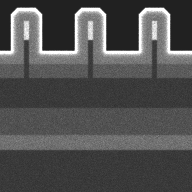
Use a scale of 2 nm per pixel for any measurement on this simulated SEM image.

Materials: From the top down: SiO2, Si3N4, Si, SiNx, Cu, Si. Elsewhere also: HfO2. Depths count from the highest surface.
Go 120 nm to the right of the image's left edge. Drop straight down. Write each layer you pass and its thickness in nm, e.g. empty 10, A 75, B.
empty 86, SiO2 26, Si3N4 28, Si 60, SiNx 54, Cu 30, Si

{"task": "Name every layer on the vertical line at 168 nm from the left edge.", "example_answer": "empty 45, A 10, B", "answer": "SiO2 112, Si3N4 28, Si 60, SiNx 54, Cu 30, Si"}